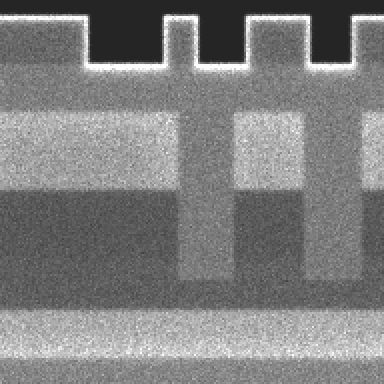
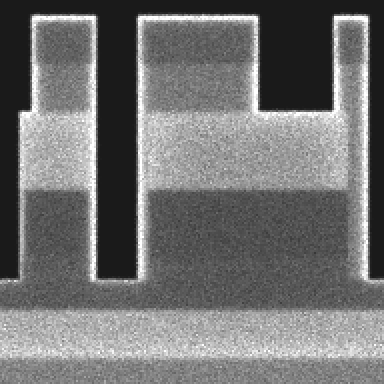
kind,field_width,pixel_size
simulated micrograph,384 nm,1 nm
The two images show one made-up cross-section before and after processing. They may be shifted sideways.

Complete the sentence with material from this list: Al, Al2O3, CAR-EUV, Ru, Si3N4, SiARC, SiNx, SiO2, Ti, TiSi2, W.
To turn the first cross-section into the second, SiO2 must be removed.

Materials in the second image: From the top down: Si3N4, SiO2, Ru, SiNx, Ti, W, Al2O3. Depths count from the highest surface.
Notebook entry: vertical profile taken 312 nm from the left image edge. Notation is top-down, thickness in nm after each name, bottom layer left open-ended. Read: empty 96, Ru 78, SiNx 68, Ti 52, W 48, Al2O3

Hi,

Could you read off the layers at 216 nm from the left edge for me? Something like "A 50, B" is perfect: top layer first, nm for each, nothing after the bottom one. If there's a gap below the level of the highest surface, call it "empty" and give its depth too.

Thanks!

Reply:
Si3N4 48, SiO2 48, Ru 78, SiNx 68, Ti 52, W 48, Al2O3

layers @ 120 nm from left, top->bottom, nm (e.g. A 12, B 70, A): empty 264, Ti 30, W 48, Al2O3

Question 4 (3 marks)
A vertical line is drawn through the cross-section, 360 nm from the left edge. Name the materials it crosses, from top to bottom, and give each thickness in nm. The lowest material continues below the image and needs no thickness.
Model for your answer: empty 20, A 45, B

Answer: Si3N4 48, SiO2 216, Ti 30, W 48, Al2O3